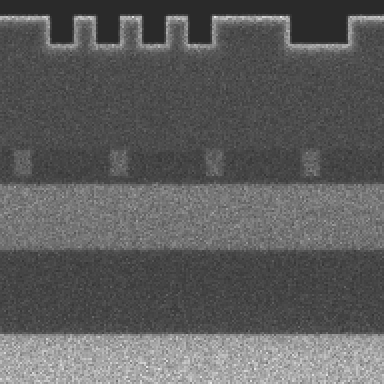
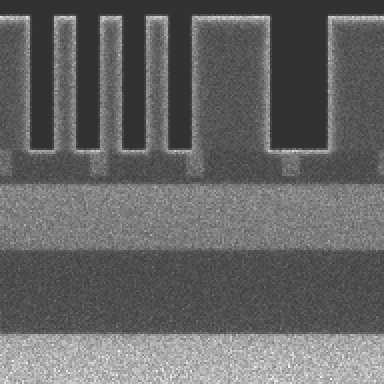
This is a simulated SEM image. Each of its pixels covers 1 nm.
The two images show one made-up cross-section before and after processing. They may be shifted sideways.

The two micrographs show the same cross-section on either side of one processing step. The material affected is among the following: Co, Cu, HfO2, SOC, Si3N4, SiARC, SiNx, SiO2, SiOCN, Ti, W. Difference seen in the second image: SOC removed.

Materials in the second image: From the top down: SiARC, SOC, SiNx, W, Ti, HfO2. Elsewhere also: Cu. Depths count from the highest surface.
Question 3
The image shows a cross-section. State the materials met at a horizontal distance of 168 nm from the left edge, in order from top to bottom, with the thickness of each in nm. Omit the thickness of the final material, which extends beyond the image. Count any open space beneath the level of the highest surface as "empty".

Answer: empty 134, SiNx 34, W 66, Ti 84, HfO2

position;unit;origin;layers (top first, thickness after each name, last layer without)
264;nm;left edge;SiARC 28, SOC 106, SiNx 34, W 66, Ti 84, HfO2